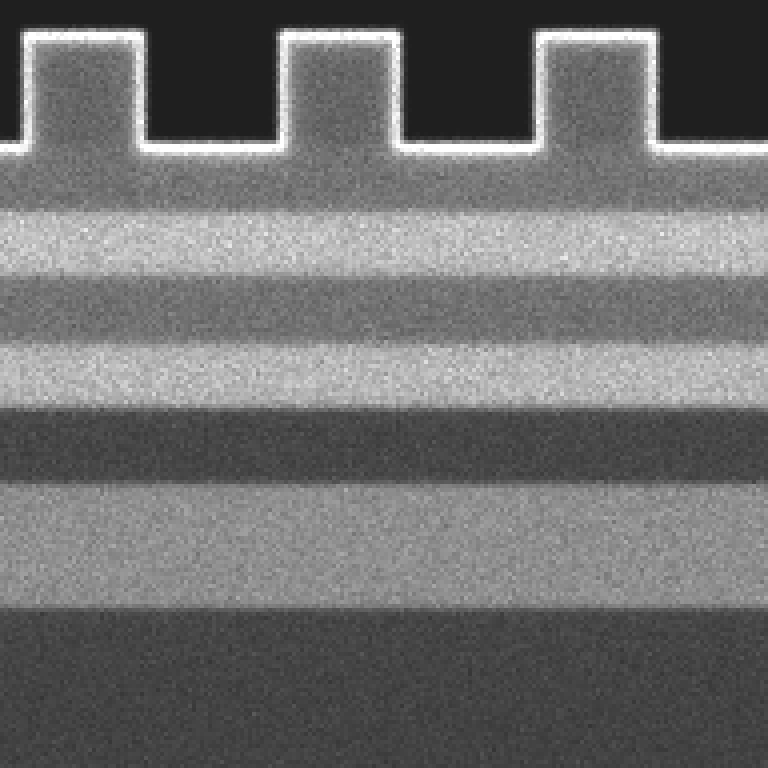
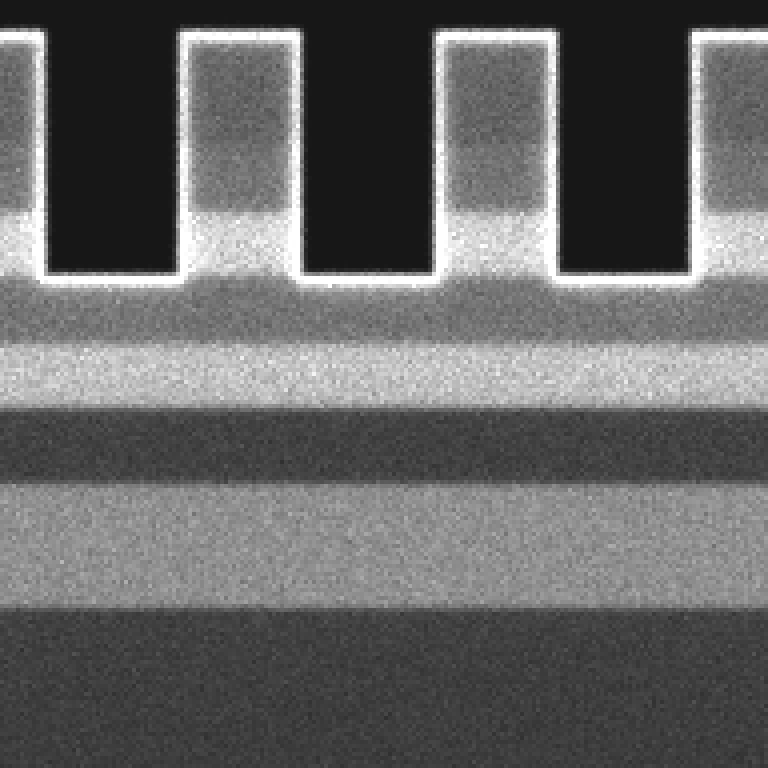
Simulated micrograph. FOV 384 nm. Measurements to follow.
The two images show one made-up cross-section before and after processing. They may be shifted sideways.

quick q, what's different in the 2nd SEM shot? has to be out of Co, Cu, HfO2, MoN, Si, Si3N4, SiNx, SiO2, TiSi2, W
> Co and Si3N4 removed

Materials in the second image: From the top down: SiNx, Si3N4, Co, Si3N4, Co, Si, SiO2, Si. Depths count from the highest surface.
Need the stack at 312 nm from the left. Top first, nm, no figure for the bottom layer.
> empty 122, Si3N4 34, Co 32, Si 38, SiO2 62, Si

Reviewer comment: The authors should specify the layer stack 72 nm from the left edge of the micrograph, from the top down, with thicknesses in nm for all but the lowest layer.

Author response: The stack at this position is empty 122, Si3N4 34, Co 32, Si 38, SiO2 62, Si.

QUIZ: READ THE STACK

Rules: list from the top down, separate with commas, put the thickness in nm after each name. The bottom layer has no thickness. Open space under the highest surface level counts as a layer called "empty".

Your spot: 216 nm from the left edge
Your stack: empty 122, Si3N4 34, Co 32, Si 38, SiO2 62, Si